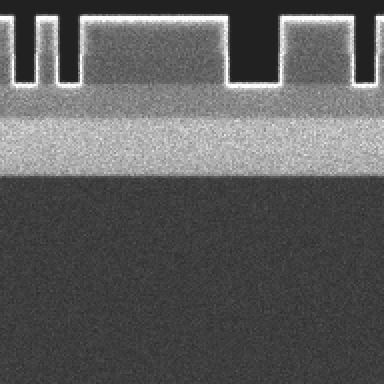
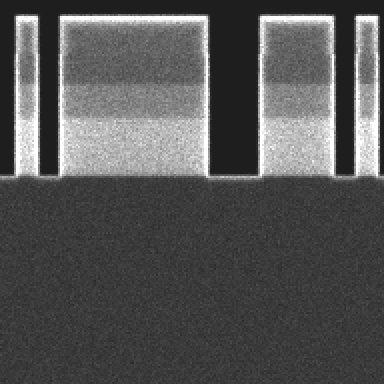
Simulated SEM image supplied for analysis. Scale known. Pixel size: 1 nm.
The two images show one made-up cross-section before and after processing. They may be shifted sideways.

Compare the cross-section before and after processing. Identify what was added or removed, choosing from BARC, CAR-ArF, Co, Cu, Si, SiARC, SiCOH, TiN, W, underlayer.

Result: Co and W removed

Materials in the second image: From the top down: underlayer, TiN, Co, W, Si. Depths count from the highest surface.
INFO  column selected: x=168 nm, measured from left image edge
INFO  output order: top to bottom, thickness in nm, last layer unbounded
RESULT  underlayer 38, TiN 30, Co 34, W 58, Si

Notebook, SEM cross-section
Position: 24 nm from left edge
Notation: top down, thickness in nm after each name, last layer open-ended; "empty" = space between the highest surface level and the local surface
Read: underlayer 38, TiN 30, Co 34, W 58, Si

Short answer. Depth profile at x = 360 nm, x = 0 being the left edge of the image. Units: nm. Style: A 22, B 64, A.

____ underlayer 38, TiN 30, Co 34, W 58, Si